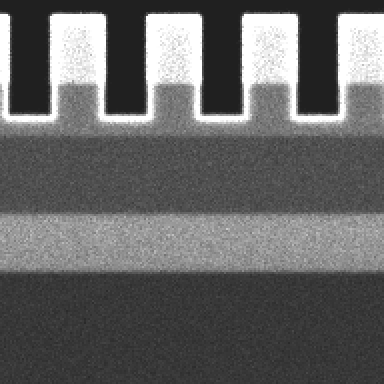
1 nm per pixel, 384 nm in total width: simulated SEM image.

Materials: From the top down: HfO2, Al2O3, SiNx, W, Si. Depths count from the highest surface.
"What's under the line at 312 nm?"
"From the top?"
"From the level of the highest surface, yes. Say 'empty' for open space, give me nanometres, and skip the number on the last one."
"empty 100, Al2O3 20, SiNx 78, W 58, Si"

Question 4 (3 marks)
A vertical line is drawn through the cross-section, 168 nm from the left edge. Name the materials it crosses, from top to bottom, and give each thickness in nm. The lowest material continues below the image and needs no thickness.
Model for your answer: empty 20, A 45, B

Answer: HfO2 68, Al2O3 52, SiNx 78, W 58, Si